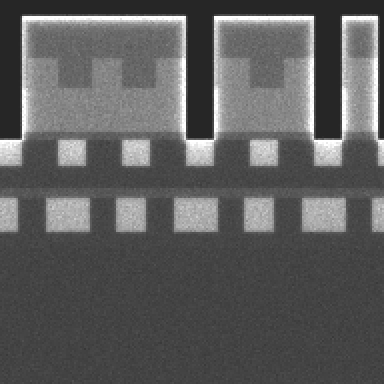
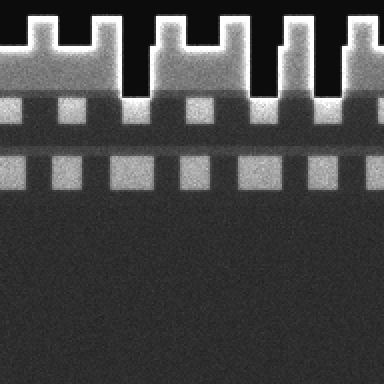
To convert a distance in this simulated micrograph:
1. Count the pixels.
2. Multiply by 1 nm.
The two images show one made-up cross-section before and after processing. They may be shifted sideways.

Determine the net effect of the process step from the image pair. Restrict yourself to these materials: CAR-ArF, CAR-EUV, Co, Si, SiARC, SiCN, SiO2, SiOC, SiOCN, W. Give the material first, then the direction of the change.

SiARC: removed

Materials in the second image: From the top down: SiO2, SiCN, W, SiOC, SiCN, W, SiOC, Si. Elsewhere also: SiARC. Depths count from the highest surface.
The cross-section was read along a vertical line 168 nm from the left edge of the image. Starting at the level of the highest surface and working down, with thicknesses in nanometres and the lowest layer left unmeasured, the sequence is SiO2 74, SiCN 8, SiOC 48, SiCN 10, SiOC 50, Si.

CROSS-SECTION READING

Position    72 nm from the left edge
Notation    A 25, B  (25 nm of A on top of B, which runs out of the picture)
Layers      empty 30, SiO2 44, SiCN 8, W 26, SiOC 22, SiCN 10, W 34, SiOC 16, Si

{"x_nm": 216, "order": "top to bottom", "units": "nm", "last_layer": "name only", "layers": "empty 30, SiO2 44, SiCN 8, SiOC 48, SiCN 10, SiOC 50, Si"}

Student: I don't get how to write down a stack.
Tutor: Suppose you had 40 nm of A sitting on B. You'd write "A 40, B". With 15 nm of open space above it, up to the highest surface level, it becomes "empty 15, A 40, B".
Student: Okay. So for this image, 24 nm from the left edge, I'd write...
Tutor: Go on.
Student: empty 30, SiO2 44, SiCN 8, SiOC 48, SiCN 10, W 34, SiOC 16, Si